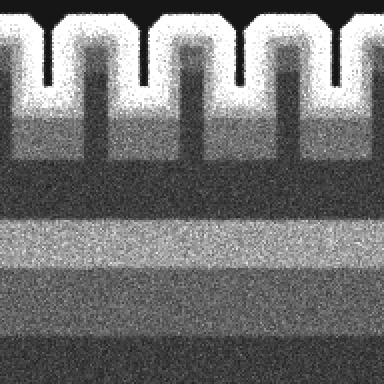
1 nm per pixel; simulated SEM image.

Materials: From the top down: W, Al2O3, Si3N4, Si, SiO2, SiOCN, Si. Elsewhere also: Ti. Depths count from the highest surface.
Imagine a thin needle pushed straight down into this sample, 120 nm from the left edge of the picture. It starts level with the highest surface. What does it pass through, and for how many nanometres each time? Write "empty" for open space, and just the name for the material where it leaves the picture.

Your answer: W 92, Al2O3 10, Si3N4 42, Si 60, SiO2 48, SiOCN 68, Si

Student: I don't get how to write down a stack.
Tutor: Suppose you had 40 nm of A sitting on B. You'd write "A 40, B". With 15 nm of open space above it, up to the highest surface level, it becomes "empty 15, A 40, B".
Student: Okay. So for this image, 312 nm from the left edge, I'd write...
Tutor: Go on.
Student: W 92, Al2O3 10, Si3N4 42, Si 60, SiO2 48, SiOCN 68, Si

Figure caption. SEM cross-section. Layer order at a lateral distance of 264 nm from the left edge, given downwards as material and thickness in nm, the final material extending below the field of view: W 92, Al2O3 10, Si3N4 42, Si 60, SiO2 48, SiOCN 68, Si